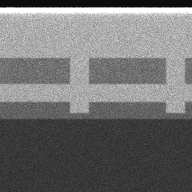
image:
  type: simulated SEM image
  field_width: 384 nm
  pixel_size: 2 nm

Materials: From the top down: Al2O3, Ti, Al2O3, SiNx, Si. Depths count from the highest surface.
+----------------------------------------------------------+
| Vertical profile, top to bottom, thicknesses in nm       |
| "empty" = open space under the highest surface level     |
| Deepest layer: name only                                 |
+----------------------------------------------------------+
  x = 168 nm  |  Al2O3 210, SiNx 12, Si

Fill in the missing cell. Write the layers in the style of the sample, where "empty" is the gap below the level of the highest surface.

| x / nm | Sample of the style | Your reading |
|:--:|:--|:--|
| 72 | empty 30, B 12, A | Al2O3 100, Ti 52, Al2O3 36, SiNx 34, Si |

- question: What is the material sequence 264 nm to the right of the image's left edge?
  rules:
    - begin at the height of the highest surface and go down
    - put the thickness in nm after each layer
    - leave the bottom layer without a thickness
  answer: Al2O3 100, Ti 52, Al2O3 36, SiNx 34, Si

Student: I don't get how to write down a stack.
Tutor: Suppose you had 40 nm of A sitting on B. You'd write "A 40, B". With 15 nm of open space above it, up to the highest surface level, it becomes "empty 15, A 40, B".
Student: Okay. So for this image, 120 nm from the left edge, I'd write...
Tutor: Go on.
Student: Al2O3 100, Ti 52, Al2O3 36, SiNx 34, Si